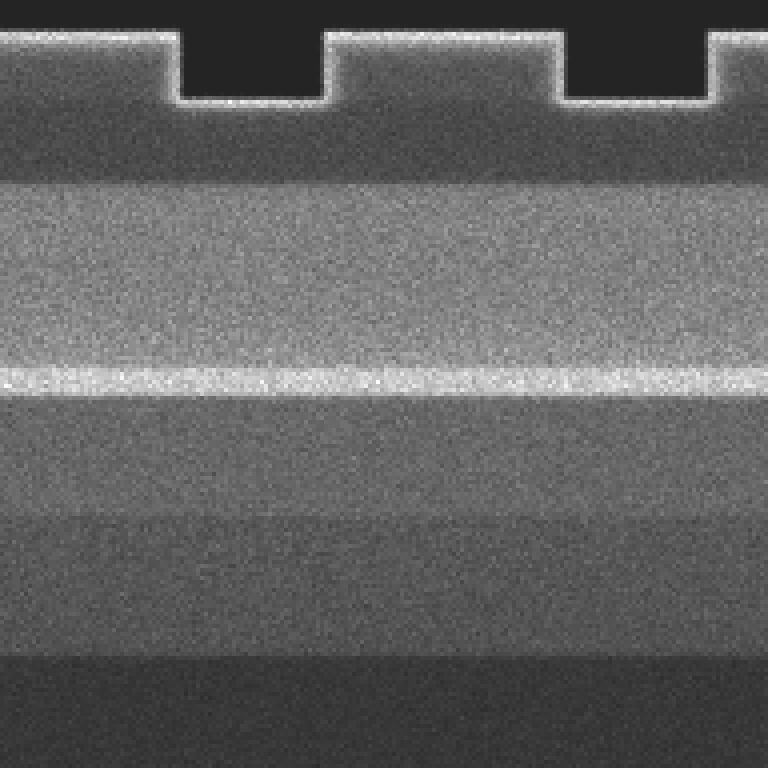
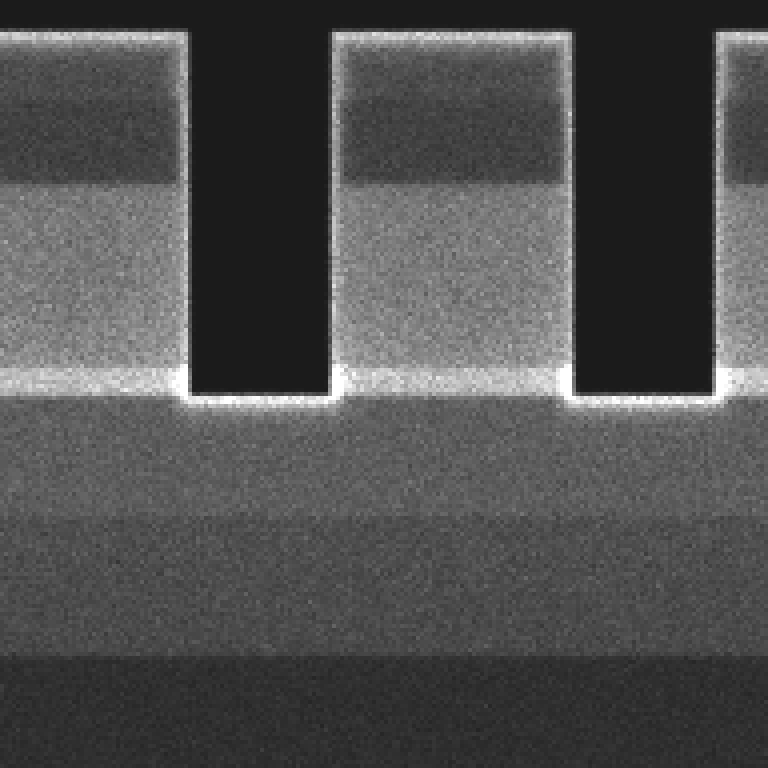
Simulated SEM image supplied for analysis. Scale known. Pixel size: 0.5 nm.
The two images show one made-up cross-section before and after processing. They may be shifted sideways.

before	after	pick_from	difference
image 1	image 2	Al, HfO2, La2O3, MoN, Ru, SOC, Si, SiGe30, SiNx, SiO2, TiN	HfO2 and Ru and SiNx removed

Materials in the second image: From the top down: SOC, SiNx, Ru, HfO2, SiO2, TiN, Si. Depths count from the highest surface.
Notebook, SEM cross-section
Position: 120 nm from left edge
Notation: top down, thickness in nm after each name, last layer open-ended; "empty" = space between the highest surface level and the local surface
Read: empty 182, SiO2 60, TiN 70, Si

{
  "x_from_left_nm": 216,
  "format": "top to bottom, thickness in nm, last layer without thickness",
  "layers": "SOC 34, SiNx 42, Ru 92, HfO2 14, SiO2 60, TiN 70, Si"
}